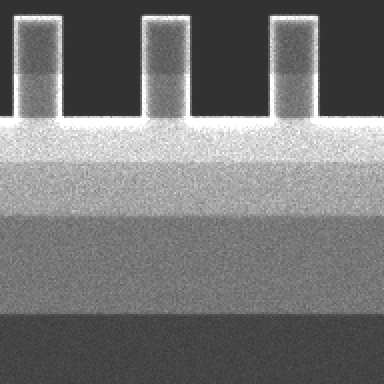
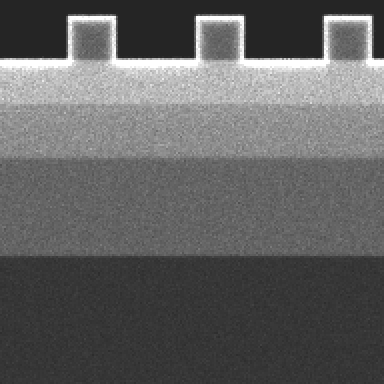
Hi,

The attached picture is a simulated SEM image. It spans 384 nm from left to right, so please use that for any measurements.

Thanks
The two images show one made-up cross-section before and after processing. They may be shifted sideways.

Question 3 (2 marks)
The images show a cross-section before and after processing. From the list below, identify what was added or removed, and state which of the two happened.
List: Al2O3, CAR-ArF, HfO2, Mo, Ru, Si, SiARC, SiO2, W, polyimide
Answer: SiARC was removed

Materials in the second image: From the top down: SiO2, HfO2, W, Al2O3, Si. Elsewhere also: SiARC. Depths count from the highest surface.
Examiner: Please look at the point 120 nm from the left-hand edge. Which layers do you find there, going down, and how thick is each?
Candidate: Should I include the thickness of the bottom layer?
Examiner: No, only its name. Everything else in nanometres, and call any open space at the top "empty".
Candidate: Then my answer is empty 44, HfO2 44, W 54, Al2O3 98, Si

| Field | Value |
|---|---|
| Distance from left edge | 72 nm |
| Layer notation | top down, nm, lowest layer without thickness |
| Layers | SiO2 44, HfO2 44, W 54, Al2O3 98, Si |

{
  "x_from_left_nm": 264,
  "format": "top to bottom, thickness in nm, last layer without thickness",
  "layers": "empty 44, HfO2 44, W 54, Al2O3 98, Si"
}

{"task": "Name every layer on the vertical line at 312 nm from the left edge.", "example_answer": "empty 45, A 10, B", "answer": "empty 44, HfO2 44, W 54, Al2O3 98, Si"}